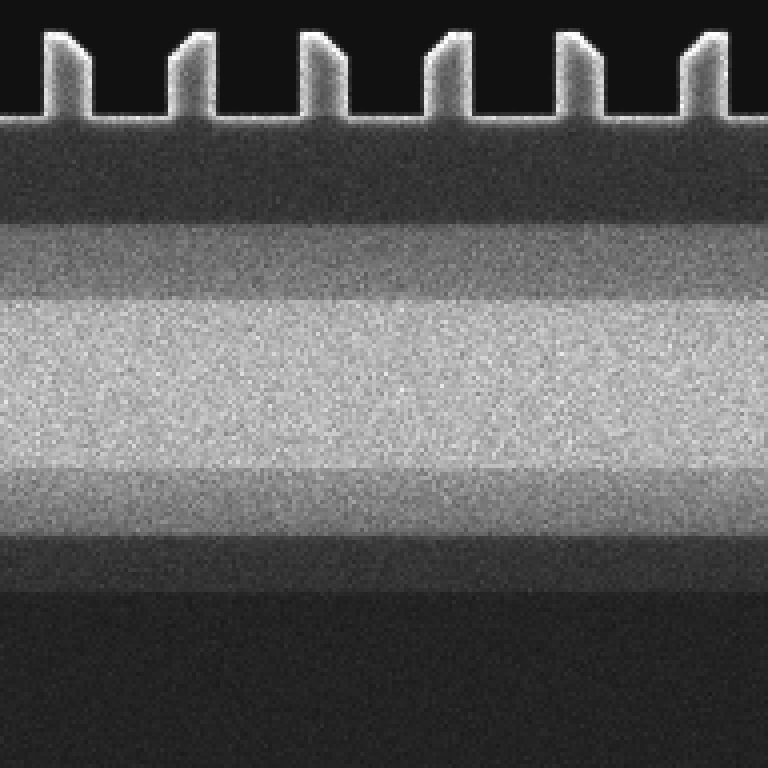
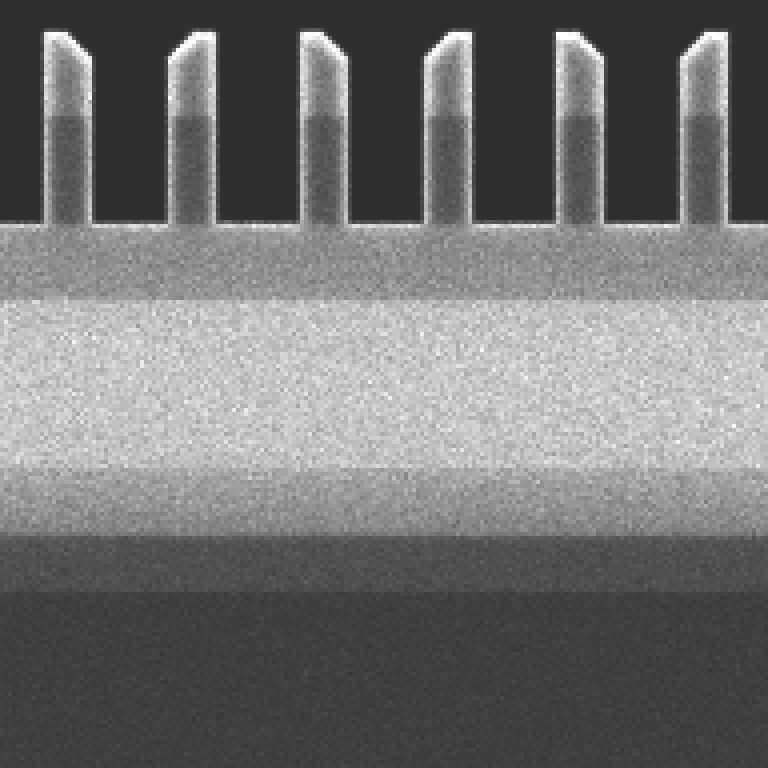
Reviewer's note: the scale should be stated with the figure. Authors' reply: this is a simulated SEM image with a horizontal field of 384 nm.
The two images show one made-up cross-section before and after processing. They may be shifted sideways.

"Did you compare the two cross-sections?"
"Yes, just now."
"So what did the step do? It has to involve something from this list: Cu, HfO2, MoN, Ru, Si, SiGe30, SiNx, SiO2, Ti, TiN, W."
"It removed SiNx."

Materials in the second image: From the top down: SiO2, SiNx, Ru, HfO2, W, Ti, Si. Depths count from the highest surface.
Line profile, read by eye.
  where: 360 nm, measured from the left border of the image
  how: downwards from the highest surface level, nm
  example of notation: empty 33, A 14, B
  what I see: SiO2 42, SiNx 54, Ru 38, HfO2 84, W 34, Ti 28, Si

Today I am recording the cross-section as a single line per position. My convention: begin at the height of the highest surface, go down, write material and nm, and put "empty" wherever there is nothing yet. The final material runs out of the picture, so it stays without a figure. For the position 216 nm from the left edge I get empty 8, SiO2 34, SiNx 54, Ru 38, HfO2 84, W 34, Ti 28, Si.